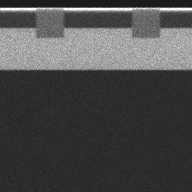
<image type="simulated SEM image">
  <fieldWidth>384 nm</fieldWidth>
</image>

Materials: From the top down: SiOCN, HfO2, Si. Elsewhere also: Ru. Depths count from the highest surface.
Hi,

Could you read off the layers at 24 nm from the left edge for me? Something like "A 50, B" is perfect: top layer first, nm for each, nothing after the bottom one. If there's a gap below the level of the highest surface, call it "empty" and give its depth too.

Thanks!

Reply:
SiOCN 40, HfO2 84, Si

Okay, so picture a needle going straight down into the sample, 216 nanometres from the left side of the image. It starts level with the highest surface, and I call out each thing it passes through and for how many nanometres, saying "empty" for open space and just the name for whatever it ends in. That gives SiOCN 40, HfO2 84, Si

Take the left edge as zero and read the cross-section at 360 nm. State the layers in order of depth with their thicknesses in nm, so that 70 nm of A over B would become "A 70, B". SiOCN 40, HfO2 84, Si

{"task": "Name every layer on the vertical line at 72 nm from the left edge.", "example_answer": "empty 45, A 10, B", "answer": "Ru 60, HfO2 64, Si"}